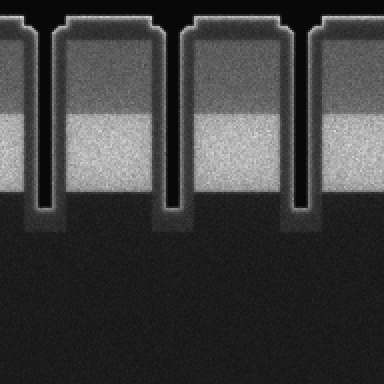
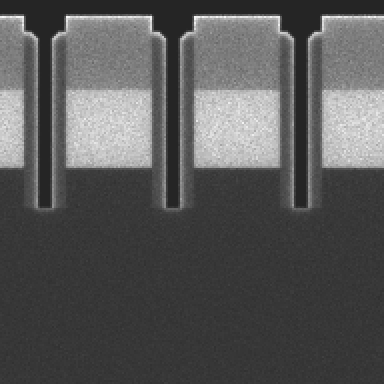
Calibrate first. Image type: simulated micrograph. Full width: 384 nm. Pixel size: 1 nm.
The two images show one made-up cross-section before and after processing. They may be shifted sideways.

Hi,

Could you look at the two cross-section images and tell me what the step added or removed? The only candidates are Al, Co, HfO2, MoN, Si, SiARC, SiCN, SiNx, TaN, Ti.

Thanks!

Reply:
removed SiNx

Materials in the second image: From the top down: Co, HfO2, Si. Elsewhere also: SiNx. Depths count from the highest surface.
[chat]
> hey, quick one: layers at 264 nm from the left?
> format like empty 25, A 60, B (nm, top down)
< Co 74, HfO2 78, Si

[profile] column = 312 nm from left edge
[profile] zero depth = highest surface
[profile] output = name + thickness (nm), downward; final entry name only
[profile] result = empty 18, SiNx 174, Si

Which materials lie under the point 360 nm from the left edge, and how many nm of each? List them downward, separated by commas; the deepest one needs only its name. Co 74, HfO2 78, Si